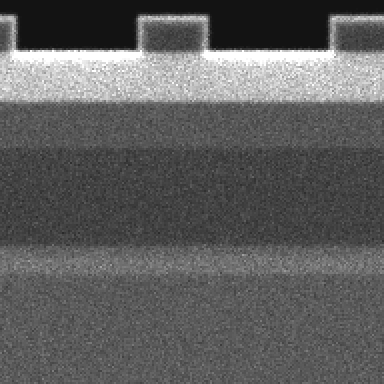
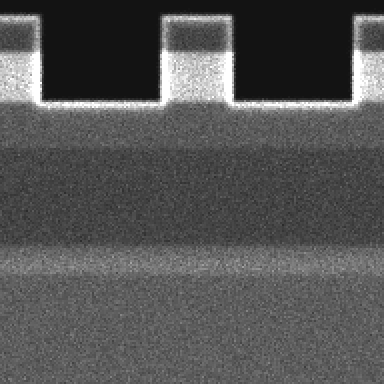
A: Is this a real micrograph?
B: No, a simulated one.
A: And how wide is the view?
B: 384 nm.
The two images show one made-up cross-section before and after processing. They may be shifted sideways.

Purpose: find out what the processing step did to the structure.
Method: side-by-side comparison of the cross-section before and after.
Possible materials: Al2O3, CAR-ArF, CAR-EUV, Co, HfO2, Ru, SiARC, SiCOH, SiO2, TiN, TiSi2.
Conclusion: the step removed HfO2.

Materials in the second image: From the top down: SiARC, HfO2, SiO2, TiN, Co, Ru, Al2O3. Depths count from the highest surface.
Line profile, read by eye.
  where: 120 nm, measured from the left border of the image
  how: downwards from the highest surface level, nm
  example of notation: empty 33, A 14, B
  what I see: empty 86, SiO2 46, TiN 98, Co 12, Ru 16, Al2O3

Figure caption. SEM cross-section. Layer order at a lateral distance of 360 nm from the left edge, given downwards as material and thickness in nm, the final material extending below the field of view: SiARC 36, HfO2 50, SiO2 46, TiN 98, Co 12, Ru 16, Al2O3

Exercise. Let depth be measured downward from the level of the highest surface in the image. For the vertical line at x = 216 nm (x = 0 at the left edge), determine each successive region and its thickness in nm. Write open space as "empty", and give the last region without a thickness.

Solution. SiARC 36, HfO2 50, SiO2 46, TiN 98, Co 12, Ru 16, Al2O3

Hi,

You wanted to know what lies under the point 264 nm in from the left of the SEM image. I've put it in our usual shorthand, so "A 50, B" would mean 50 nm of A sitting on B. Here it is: empty 86, SiO2 46, TiN 98, Co 12, Ru 16, Al2O3